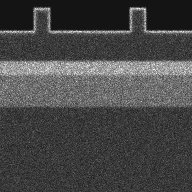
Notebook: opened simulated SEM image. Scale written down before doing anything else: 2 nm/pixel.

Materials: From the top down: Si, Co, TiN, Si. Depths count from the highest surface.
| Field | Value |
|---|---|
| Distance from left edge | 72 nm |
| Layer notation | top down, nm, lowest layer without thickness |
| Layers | Si 106, Co 28, TiN 64, Si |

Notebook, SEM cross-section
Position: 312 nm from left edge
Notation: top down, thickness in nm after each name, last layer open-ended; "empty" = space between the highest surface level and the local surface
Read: empty 46, Si 60, Co 28, TiN 64, Si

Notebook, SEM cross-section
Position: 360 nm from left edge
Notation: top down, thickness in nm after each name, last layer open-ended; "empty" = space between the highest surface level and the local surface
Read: empty 46, Si 60, Co 28, TiN 64, Si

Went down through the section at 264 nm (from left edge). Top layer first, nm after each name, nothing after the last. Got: Si 106, Co 28, TiN 64, Si